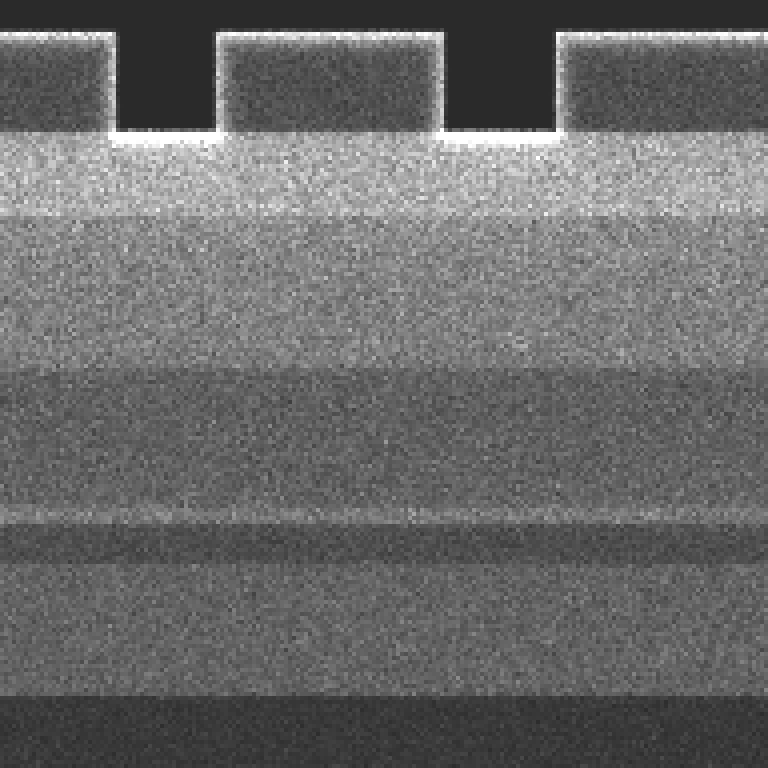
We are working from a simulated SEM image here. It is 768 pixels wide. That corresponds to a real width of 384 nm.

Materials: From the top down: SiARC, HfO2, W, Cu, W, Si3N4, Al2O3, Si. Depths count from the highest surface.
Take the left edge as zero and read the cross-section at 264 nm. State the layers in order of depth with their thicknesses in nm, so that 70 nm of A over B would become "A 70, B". empty 50, HfO2 42, W 76, Cu 70, W 8, Si3N4 20, Al2O3 66, Si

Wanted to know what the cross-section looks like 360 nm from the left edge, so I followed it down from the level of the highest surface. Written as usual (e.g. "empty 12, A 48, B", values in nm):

SiARC 50, HfO2 42, W 76, Cu 70, W 8, Si3N4 20, Al2O3 66, Si